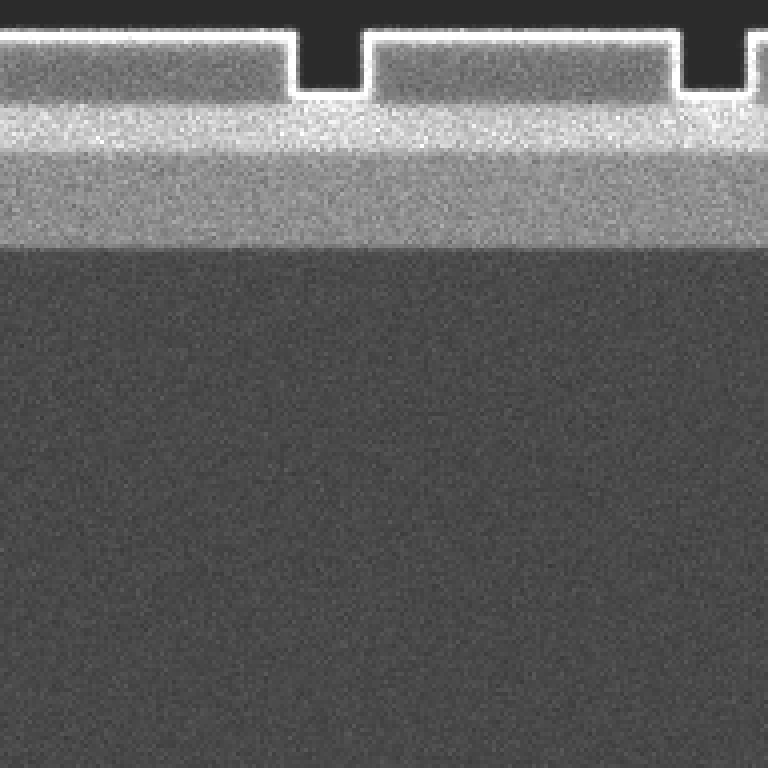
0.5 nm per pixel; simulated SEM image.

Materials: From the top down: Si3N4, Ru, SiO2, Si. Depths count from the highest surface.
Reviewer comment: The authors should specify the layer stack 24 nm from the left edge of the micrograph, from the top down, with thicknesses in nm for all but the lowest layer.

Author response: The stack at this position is Si3N4 36, Ru 24, SiO2 48, Si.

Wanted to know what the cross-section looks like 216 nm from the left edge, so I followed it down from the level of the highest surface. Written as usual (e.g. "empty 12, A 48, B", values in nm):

Si3N4 36, Ru 24, SiO2 48, Si